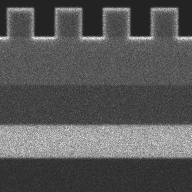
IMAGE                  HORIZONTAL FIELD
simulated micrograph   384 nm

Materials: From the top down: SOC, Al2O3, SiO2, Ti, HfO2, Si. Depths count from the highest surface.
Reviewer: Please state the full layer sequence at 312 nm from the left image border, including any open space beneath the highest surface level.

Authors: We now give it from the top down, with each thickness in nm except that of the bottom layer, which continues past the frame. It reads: SOC 58, Al2O3 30, SiO2 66, Ti 80, HfO2 66, Si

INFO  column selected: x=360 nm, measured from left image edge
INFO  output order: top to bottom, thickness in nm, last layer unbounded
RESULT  empty 58, Al2O3 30, SiO2 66, Ti 80, HfO2 66, Si